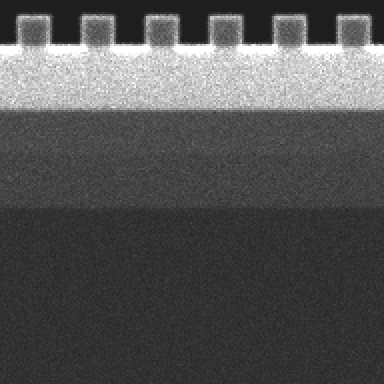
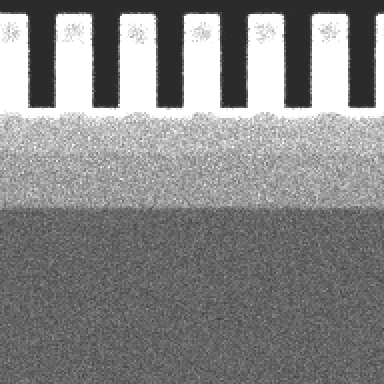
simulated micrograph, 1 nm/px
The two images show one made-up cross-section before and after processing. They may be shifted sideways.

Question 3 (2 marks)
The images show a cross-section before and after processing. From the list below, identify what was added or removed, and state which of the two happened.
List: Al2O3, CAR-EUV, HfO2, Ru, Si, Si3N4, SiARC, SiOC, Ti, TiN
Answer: HfO2 was removed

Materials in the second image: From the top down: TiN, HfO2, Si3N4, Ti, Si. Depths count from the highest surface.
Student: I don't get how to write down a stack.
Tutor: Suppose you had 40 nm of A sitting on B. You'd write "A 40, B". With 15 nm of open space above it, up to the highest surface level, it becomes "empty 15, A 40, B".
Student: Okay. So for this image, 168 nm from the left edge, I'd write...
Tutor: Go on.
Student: empty 94, Si3N4 44, Ti 54, Si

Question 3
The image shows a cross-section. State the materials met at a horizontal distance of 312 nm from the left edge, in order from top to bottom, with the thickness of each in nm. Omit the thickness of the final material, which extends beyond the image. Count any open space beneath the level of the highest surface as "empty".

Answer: empty 94, Si3N4 44, Ti 54, Si